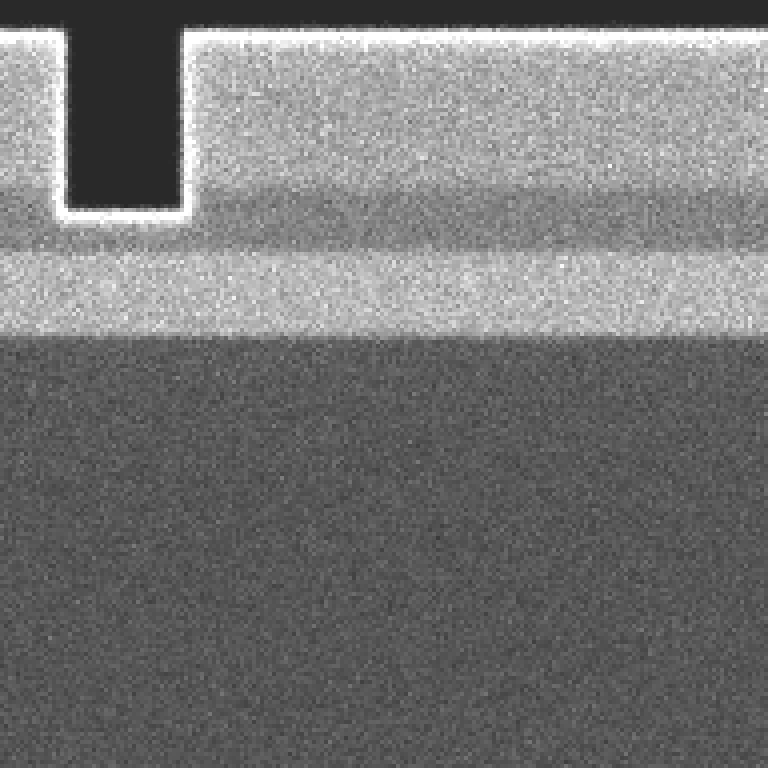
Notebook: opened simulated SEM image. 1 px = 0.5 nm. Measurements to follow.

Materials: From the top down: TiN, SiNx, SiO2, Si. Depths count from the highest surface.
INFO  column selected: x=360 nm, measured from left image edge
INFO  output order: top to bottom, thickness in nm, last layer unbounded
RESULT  TiN 78, SiNx 32, SiO2 42, Si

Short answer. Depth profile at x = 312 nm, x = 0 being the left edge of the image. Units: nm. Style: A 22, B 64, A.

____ TiN 78, SiNx 32, SiO2 42, Si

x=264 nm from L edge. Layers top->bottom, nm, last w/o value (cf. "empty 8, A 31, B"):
TiN 78, SiNx 32, SiO2 42, Si